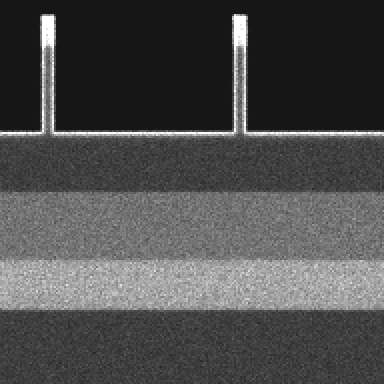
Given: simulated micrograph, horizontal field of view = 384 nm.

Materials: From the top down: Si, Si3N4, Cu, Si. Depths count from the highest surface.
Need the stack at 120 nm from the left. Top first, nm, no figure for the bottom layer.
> empty 116, Si 60, Si3N4 68, Cu 50, Si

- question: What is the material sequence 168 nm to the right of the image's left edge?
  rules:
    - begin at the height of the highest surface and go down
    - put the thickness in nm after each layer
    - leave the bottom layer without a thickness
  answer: empty 116, Si 60, Si3N4 68, Cu 50, Si